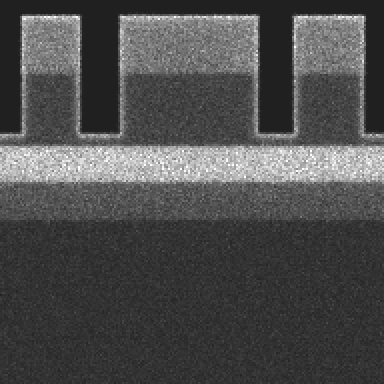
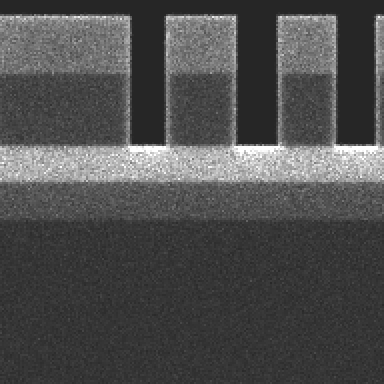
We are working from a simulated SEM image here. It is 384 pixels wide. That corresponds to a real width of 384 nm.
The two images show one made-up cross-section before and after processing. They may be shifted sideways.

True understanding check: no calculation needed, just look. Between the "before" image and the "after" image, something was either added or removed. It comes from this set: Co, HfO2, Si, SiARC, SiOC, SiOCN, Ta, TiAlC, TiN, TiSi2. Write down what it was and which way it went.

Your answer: SiOCN (removed)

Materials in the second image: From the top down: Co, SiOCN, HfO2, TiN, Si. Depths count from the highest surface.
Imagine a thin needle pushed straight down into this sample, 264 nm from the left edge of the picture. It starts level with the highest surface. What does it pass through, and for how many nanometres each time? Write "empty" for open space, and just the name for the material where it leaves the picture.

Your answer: empty 130, HfO2 36, TiN 38, Si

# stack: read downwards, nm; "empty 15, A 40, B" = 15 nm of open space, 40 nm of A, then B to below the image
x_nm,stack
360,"empty 130, HfO2 36, TiN 38, Si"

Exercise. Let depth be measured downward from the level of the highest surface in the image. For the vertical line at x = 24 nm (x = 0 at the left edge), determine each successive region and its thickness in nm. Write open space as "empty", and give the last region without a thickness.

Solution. Co 58, SiOCN 72, HfO2 36, TiN 38, Si